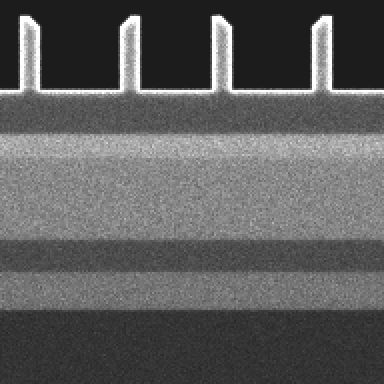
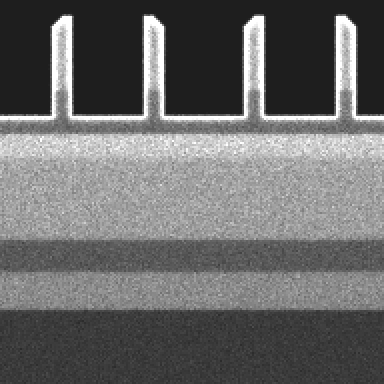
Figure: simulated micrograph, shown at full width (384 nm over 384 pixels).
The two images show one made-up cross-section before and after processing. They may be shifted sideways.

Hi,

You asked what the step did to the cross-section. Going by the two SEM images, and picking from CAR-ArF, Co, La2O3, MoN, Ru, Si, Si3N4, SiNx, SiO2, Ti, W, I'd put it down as Si3N4, removed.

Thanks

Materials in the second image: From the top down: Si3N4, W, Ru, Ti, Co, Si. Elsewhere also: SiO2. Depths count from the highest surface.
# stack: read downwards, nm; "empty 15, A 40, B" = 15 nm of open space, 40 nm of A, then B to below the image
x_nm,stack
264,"empty 100, Si3N4 18, W 24, Ru 82, Ti 32, Co 38, Si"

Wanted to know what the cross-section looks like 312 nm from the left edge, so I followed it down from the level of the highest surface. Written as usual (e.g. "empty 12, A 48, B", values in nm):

empty 100, Si3N4 18, W 24, Ru 82, Ti 32, Co 38, Si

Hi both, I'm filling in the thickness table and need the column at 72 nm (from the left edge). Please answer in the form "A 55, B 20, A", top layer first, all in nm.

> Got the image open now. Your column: empty 100, Si3N4 18, W 24, Ru 82, Ti 32, Co 38, Si